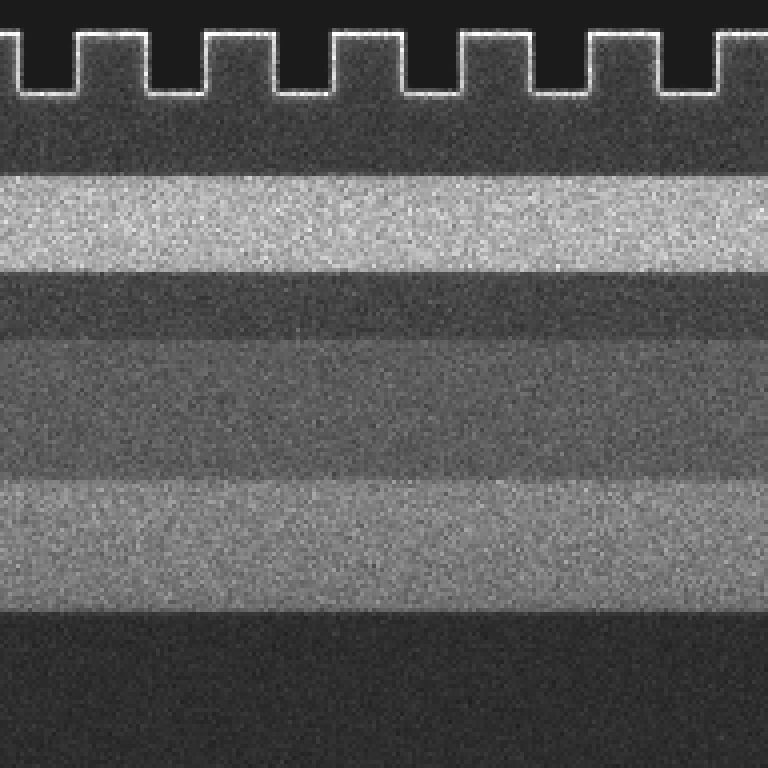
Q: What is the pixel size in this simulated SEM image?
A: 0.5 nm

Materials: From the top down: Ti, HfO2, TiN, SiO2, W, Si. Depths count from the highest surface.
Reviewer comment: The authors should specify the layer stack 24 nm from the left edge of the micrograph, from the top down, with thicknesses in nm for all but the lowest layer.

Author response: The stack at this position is empty 30, Ti 42, HfO2 48, TiN 34, SiO2 70, W 66, Si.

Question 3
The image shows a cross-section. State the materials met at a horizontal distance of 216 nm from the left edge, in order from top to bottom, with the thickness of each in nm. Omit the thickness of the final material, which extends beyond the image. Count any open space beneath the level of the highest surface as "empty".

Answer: empty 30, Ti 42, HfO2 48, TiN 34, SiO2 70, W 66, Si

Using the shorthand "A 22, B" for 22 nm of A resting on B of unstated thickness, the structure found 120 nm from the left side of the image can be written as Ti 72, HfO2 48, TiN 34, SiO2 70, W 66, Si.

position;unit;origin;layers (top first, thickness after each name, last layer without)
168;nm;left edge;Ti 72, HfO2 48, TiN 34, SiO2 70, W 66, Si